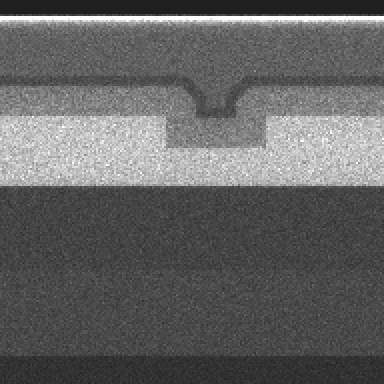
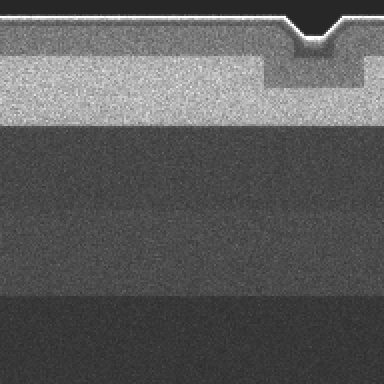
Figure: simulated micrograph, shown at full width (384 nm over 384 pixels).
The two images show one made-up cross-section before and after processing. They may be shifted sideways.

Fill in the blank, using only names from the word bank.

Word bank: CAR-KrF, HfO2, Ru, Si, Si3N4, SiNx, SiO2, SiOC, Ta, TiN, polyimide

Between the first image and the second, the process removed SiO2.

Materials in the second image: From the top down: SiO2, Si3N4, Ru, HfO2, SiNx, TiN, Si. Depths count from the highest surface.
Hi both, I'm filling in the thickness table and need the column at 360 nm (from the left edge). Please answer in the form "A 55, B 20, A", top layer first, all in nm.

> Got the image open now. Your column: Si3N4 10, Ru 62, HfO2 38, SiNx 84, TiN 86, Si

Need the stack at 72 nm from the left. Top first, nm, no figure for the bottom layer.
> Si3N4 10, Ru 30, HfO2 70, SiNx 84, TiN 86, Si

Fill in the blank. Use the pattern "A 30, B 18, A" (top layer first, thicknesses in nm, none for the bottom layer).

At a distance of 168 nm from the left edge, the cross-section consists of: Si3N4 10, Ru 30, HfO2 70, SiNx 84, TiN 86, Si